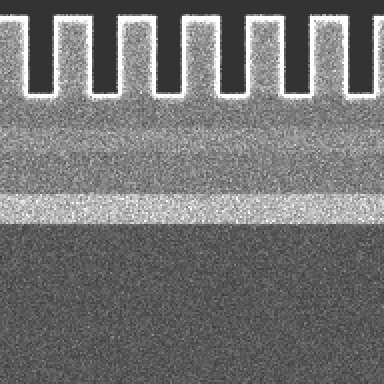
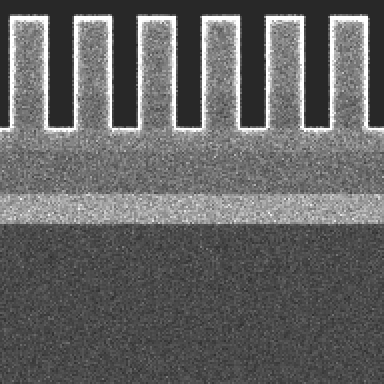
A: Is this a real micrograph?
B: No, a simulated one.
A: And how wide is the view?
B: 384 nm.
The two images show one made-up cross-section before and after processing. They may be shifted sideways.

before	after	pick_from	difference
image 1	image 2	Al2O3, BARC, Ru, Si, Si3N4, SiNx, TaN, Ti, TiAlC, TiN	SiNx removed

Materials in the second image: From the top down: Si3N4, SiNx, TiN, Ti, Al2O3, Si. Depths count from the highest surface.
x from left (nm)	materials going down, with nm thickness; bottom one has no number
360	Si3N4 78, SiNx 34, TiN 24, Ti 42, Al2O3 30, Si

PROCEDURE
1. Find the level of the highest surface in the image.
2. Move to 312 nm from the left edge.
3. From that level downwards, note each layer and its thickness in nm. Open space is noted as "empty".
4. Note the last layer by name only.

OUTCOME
empty 112, TiN 24, Ti 42, Al2O3 30, Si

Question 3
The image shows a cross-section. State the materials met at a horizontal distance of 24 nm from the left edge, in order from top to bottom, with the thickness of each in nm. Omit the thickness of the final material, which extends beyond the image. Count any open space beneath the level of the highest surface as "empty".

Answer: Si3N4 78, SiNx 34, TiN 24, Ti 42, Al2O3 30, Si